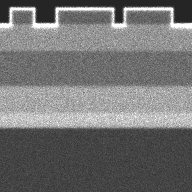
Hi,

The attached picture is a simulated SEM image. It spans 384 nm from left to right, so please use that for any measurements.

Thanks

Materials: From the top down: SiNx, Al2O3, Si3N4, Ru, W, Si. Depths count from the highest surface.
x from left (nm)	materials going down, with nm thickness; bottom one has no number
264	SiNx 32, Al2O3 54, Si3N4 70, Ru 54, W 30, Si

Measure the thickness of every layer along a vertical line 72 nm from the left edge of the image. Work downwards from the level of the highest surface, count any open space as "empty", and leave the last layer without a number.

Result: empty 32, Al2O3 54, Si3N4 70, Ru 54, W 30, Si